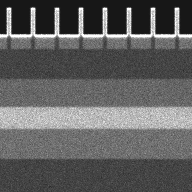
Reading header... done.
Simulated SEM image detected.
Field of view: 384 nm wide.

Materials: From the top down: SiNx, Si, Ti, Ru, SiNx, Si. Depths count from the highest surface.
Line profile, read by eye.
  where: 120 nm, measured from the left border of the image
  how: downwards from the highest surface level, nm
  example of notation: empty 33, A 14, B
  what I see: empty 54, SiNx 28, Si 60, Ti 56, Ru 44, SiNx 60, Si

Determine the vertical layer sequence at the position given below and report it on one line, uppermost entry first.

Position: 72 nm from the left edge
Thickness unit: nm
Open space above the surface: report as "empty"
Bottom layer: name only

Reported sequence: empty 54, SiNx 28, Si 60, Ti 56, Ru 44, SiNx 60, Si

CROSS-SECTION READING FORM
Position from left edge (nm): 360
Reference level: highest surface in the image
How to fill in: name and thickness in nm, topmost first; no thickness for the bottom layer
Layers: empty 54, SiNx 28, Si 60, Ti 56, Ru 44, SiNx 60, Si